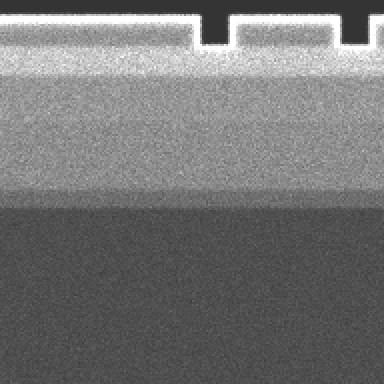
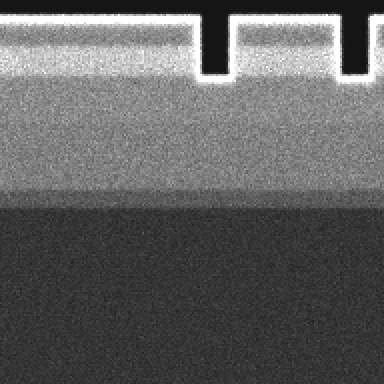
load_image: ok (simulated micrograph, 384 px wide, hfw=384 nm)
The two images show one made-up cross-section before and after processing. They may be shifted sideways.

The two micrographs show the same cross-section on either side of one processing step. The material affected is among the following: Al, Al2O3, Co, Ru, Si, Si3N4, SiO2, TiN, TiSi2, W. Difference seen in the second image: W removed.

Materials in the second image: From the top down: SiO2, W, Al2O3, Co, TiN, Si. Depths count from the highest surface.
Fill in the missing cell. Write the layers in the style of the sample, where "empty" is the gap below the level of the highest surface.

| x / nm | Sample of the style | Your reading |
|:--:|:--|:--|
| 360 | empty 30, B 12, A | empty 60, Al2O3 46, Co 68, TiN 18, Si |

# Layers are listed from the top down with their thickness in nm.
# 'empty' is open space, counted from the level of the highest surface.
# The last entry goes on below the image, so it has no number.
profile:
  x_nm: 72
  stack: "SiO2 30, W 30, Al2O3 46, Co 68, TiN 18, Si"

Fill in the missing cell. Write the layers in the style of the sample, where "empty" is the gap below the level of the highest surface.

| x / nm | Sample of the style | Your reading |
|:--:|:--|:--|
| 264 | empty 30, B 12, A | SiO2 30, W 30, Al2O3 46, Co 68, TiN 18, Si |